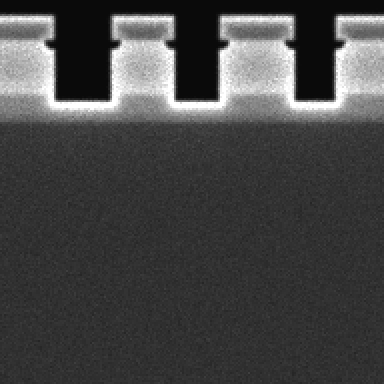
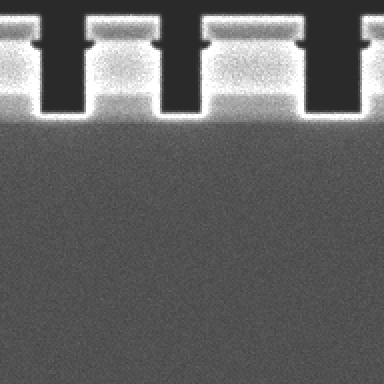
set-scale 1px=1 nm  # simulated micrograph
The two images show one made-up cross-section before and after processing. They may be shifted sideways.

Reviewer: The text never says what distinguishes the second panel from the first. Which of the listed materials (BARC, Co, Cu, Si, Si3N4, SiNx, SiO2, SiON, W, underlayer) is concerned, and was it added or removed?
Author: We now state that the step removed SiO2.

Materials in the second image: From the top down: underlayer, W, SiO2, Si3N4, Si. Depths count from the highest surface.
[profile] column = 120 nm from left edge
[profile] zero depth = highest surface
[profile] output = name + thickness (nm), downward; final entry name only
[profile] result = underlayer 24, W 54, SiO2 20, Si3N4 8, Si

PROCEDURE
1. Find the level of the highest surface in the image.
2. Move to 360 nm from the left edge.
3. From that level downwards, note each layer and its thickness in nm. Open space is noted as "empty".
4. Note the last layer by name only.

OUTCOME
empty 98, Si3N4 8, Si